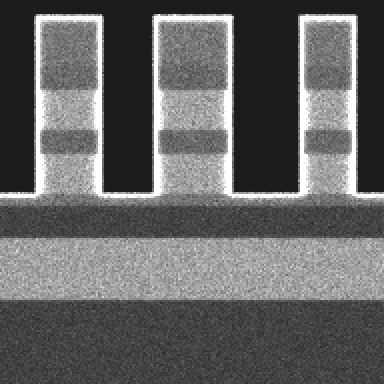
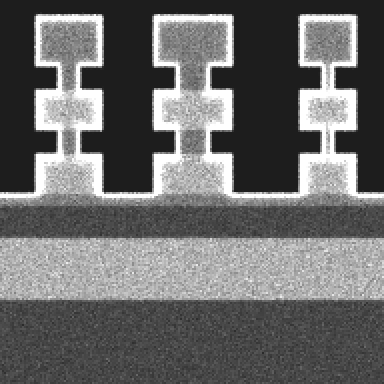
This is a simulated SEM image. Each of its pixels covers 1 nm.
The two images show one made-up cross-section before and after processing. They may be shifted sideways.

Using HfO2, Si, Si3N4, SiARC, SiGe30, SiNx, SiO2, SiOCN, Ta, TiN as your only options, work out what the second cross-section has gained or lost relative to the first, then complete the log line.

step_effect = removed SiNx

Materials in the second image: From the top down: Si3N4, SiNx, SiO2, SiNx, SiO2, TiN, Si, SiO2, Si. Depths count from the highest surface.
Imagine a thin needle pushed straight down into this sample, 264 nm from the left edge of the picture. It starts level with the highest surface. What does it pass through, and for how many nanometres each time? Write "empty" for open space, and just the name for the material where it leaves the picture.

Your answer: empty 178, TiN 12, Si 32, SiO2 62, Si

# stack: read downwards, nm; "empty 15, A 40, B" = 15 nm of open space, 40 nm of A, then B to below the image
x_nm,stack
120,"empty 178, TiN 12, Si 32, SiO2 62, Si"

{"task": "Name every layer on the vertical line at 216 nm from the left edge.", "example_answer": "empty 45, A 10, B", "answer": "Si3N4 50, empty 24, SiO2 40, empty 24, SiO2 40, TiN 12, Si 32, SiO2 62, Si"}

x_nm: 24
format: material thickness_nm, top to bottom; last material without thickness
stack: empty 178, TiN 12, Si 32, SiO2 62, Si